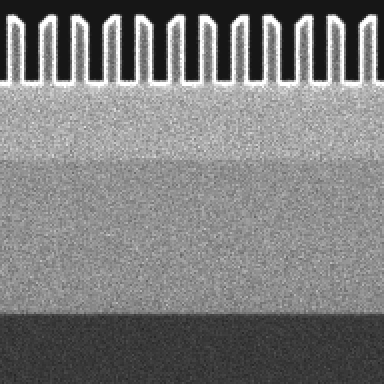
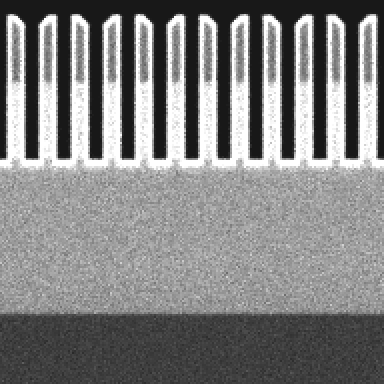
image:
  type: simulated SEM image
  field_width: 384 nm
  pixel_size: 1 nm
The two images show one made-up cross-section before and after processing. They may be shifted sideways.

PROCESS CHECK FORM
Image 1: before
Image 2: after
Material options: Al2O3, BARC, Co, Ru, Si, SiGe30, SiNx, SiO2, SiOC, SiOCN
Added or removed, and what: removed, Ru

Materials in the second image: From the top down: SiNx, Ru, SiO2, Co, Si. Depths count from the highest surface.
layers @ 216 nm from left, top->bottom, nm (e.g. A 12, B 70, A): empty 144, SiO2 88, Co 66, Si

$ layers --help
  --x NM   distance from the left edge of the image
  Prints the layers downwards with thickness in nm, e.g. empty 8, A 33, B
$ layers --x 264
SiNx 66, Ru 78, SiO2 88, Co 66, Si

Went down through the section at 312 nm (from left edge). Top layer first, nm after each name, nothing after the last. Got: empty 144, SiO2 88, Co 66, Si